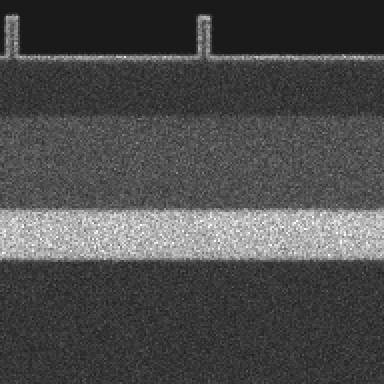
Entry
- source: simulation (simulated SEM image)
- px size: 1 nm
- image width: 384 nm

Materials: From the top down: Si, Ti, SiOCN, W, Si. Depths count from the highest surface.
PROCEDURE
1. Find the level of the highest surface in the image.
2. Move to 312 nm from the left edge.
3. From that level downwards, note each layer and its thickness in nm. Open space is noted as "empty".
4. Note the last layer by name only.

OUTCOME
empty 40, Si 60, Ti 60, SiOCN 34, W 50, Si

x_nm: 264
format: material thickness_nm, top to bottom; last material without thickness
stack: empty 40, Si 60, Ti 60, SiOCN 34, W 50, Si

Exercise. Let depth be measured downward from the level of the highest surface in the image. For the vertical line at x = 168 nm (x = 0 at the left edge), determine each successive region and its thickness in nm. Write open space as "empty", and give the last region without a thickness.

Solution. empty 40, Si 60, Ti 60, SiOCN 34, W 50, Si